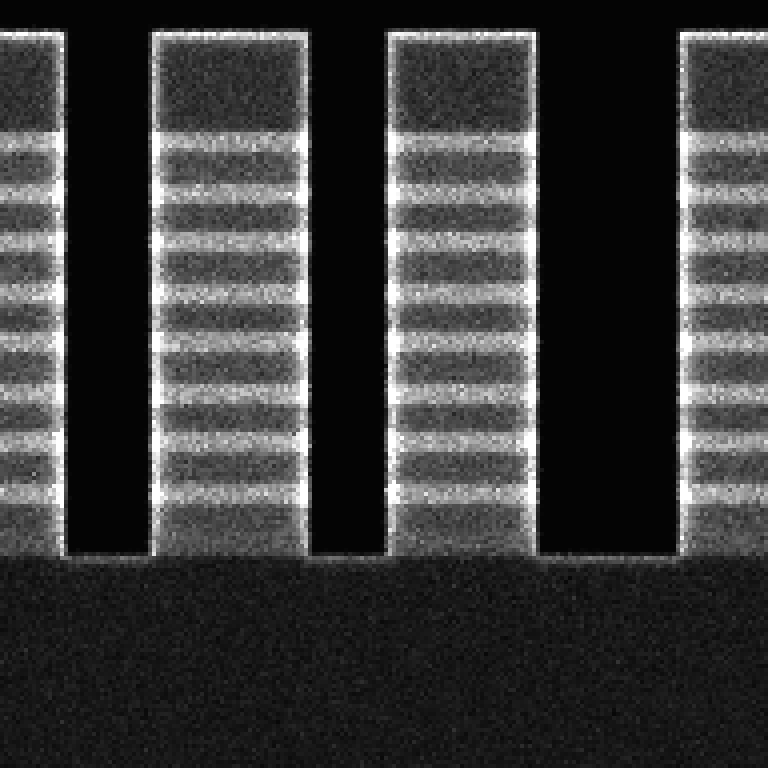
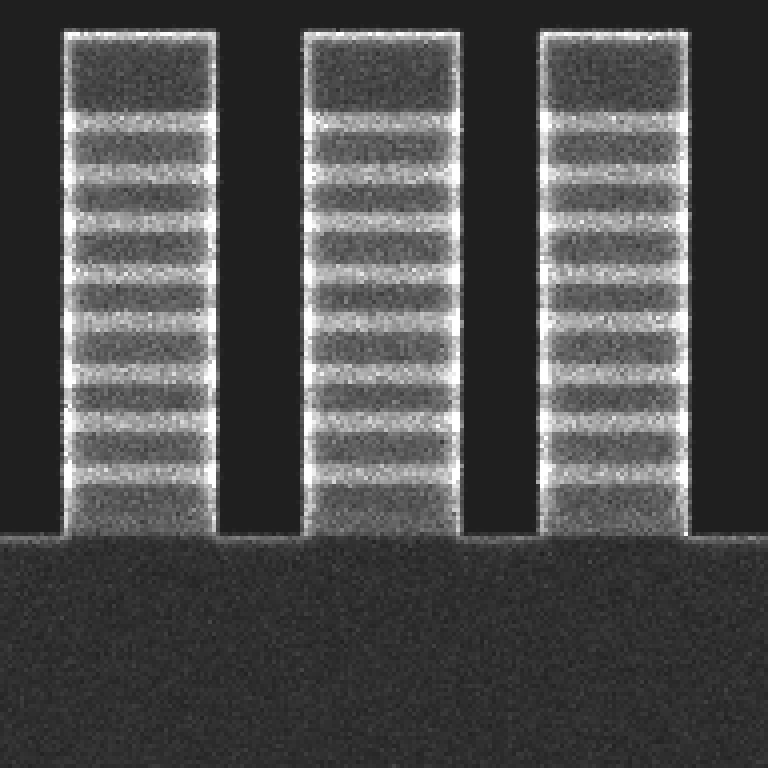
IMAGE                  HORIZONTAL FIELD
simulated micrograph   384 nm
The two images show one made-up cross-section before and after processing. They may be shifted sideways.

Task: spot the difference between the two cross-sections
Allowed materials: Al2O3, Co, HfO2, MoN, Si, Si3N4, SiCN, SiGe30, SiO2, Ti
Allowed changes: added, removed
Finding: removed Si3N4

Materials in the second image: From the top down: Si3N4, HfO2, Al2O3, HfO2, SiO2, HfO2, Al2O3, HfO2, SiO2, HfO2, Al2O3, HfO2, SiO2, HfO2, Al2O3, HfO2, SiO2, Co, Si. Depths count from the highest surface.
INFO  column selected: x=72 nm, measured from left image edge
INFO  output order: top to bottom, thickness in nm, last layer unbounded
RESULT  Si3N4 40, HfO2 10, Al2O3 16, HfO2 10, SiO2 14, HfO2 10, Al2O3 16, HfO2 10, SiO2 14, HfO2 10, Al2O3 16, HfO2 10, SiO2 14, HfO2 10, Al2O3 16, HfO2 10, SiO2 14, Co 12, Si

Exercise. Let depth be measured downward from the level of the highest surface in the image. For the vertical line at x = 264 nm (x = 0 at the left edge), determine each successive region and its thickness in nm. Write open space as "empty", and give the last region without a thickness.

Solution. empty 252, Si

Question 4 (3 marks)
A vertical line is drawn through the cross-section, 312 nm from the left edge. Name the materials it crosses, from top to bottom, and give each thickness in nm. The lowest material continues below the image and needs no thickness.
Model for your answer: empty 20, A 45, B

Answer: Si3N4 40, HfO2 10, Al2O3 16, HfO2 10, SiO2 14, HfO2 10, Al2O3 16, HfO2 10, SiO2 14, HfO2 10, Al2O3 16, HfO2 10, SiO2 14, HfO2 10, Al2O3 16, HfO2 10, SiO2 14, Co 12, Si